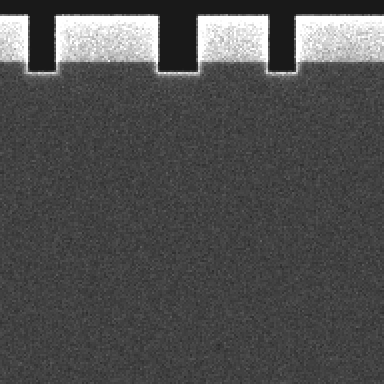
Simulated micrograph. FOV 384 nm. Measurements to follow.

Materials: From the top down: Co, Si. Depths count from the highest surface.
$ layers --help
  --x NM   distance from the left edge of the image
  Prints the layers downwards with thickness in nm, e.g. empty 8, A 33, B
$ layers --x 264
Co 46, Si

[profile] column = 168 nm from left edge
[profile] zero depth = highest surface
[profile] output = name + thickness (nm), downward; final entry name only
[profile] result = empty 56, Si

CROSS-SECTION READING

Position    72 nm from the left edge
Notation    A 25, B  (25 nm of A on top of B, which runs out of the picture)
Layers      Co 46, Si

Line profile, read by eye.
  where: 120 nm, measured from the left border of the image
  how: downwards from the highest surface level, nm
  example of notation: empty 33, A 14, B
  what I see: Co 46, Si